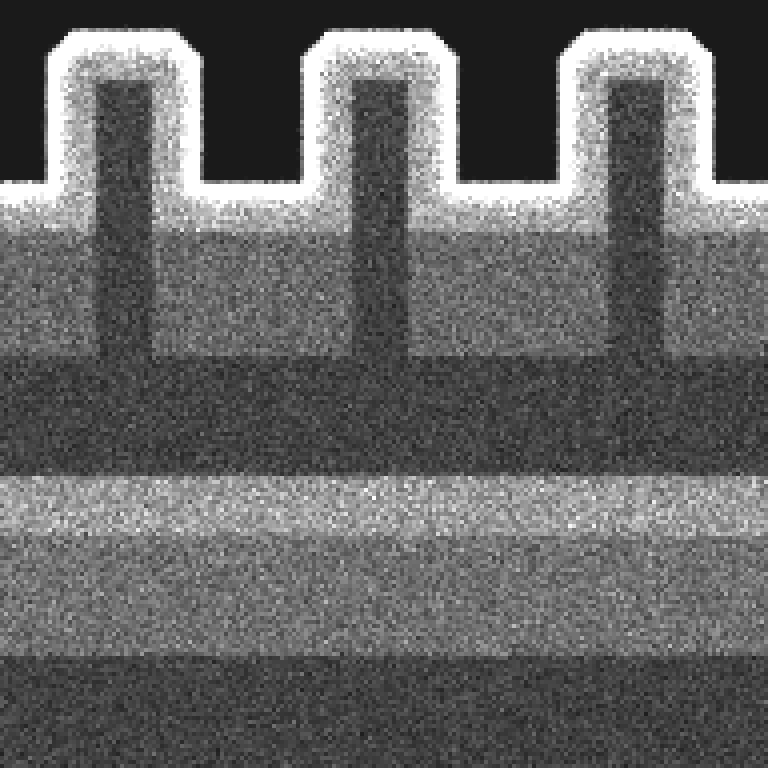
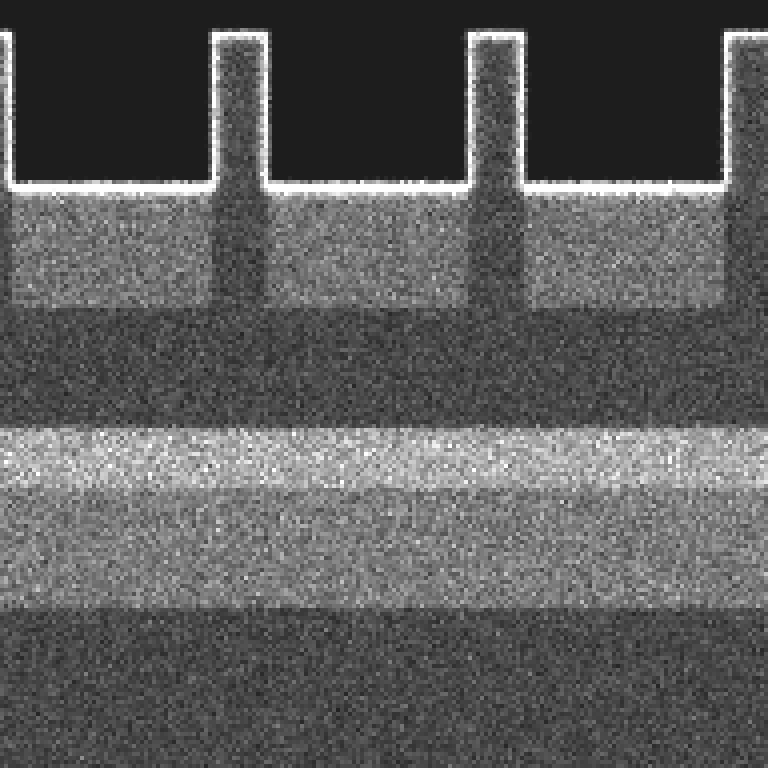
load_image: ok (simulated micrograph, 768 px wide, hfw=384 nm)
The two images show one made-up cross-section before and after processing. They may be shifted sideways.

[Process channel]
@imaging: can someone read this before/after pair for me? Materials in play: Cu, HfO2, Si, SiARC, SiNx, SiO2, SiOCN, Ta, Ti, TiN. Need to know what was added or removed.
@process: SiO2 removed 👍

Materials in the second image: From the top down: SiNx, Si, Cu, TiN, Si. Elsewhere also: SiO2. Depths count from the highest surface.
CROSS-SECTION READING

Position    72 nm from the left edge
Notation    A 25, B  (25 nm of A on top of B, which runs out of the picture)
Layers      empty 76, SiNx 62, Si 60, Cu 30, TiN 60, Si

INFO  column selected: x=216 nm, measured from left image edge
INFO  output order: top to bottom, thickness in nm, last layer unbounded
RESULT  empty 76, SiNx 62, Si 60, Cu 30, TiN 60, Si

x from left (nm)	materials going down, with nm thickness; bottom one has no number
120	Si 198, Cu 30, TiN 60, Si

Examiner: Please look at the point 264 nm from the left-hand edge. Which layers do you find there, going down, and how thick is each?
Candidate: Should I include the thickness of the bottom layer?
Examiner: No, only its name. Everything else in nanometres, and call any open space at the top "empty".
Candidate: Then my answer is empty 76, SiNx 62, Si 60, Cu 30, TiN 60, Si